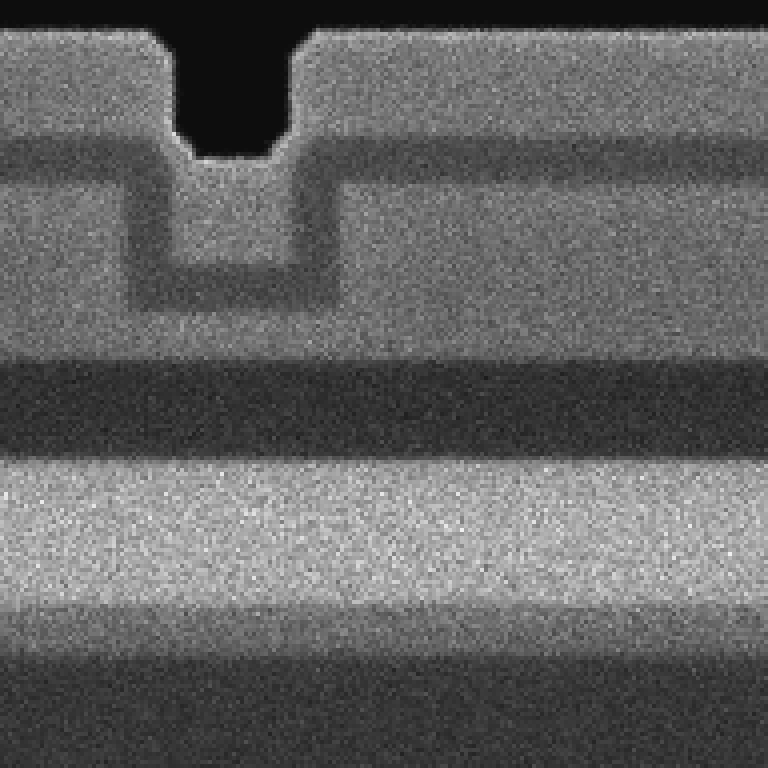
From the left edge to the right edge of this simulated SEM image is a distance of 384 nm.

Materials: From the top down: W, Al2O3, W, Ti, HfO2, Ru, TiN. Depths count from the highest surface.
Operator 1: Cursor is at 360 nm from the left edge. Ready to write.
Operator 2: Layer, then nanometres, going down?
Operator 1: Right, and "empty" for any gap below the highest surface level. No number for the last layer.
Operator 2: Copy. W 52, Al2O3 24, W 88, Ti 50, HfO2 72, Ru 26, TiN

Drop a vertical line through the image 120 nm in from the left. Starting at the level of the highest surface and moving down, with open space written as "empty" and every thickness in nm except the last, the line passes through empty 64, W 52, Al2O3 24, W 24, Ti 50, HfO2 72, Ru 26, TiN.